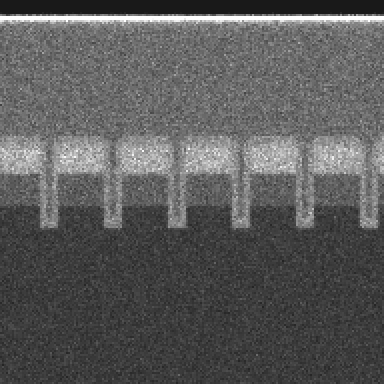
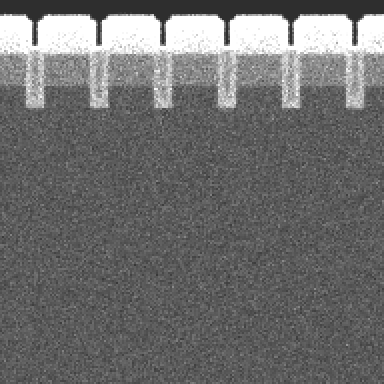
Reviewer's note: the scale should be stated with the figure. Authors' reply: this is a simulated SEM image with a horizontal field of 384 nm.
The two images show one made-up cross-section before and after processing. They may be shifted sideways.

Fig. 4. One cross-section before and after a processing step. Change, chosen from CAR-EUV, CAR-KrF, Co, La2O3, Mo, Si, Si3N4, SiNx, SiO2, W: Si3N4 removed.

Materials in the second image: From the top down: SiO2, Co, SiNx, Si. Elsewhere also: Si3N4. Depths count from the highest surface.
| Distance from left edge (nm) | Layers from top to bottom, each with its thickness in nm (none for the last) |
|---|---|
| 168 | empty 4, SiO2 88, Si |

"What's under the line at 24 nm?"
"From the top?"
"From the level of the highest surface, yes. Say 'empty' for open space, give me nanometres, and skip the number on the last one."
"SiO2 10, Co 28, SiNx 32, Si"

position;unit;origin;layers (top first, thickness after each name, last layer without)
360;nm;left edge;empty 4, SiO2 88, Si